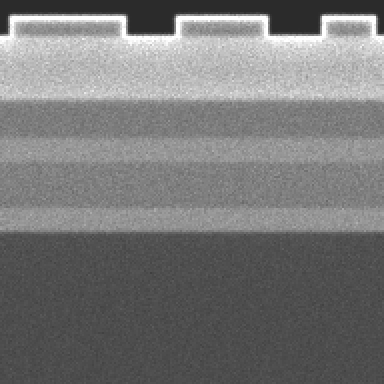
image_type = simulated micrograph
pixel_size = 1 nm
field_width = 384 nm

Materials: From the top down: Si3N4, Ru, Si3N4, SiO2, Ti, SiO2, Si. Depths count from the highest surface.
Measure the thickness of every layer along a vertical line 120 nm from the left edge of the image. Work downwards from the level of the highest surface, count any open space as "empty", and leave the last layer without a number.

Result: Si3N4 20, Ru 64, Si3N4 38, SiO2 24, Ti 46, SiO2 24, Si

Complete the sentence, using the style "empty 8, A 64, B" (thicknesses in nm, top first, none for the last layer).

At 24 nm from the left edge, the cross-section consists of Si3N4 20, Ru 64, Si3N4 38, SiO2 24, Ti 46, SiO2 24, Si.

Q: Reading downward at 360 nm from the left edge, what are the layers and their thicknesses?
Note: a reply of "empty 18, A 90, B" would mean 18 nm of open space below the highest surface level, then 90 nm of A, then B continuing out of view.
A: Si3N4 20, Ru 64, Si3N4 38, SiO2 24, Ti 46, SiO2 24, Si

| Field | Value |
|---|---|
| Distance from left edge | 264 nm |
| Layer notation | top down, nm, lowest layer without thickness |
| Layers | Si3N4 20, Ru 64, Si3N4 38, SiO2 24, Ti 46, SiO2 24, Si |